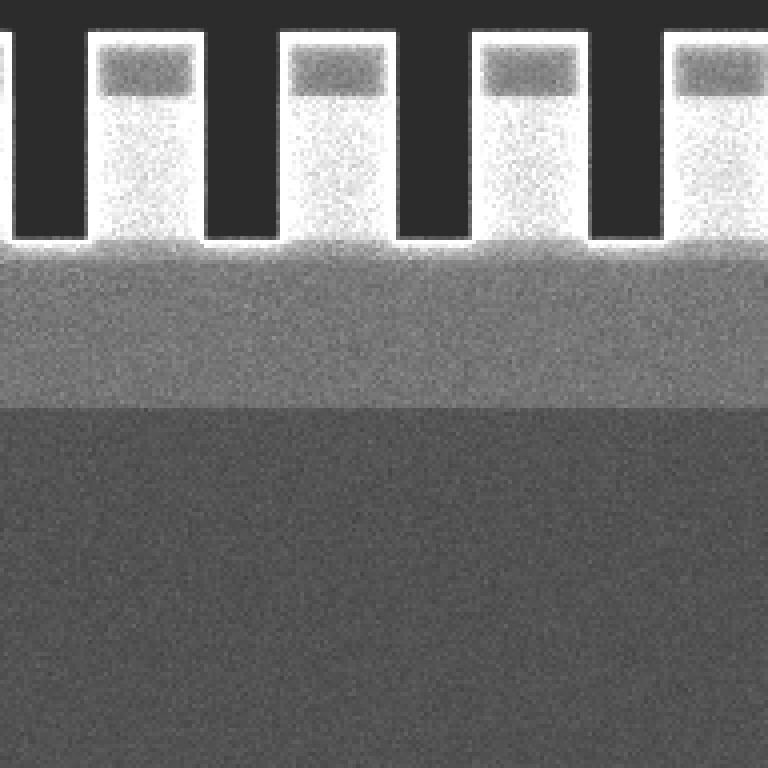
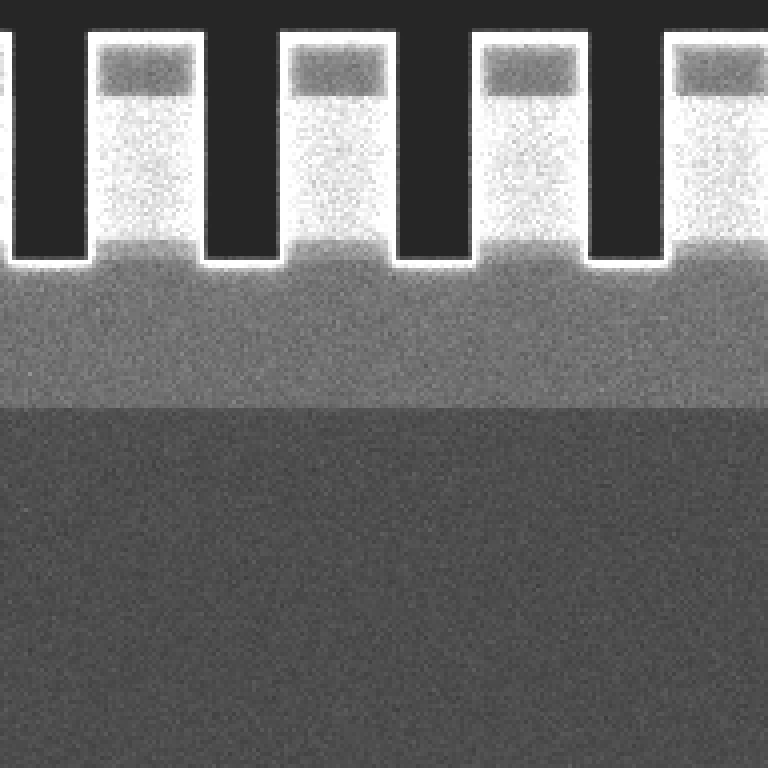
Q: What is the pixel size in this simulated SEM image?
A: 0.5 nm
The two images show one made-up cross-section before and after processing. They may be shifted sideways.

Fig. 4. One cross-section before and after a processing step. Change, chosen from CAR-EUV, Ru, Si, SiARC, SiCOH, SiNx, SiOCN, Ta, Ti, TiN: TiN removed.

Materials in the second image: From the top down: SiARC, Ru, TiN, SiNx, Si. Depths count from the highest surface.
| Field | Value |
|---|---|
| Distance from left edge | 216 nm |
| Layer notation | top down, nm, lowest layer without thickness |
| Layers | empty 114, SiNx 74, Si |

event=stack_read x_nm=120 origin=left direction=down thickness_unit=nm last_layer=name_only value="empty 114, SiNx 74, Si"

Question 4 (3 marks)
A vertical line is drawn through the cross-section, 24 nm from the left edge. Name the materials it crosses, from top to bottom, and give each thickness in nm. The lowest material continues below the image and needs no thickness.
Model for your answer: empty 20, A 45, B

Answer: empty 114, SiNx 74, Si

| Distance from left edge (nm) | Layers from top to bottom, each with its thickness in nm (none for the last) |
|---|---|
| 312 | empty 114, SiNx 74, Si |